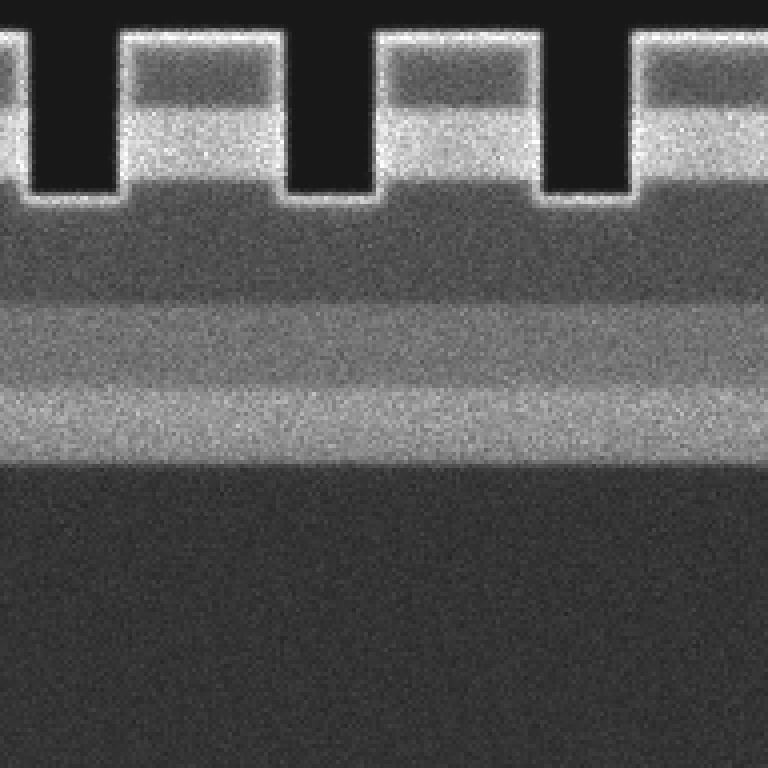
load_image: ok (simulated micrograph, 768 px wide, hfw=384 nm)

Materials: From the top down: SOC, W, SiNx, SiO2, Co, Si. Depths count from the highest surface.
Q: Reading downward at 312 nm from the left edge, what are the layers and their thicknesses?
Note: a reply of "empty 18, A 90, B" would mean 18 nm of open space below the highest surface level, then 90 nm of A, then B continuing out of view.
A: empty 82, SiNx 54, SiO2 42, Co 38, Si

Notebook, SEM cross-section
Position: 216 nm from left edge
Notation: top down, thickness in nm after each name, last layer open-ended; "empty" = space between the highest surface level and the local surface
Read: SOC 38, W 36, SiNx 62, SiO2 42, Co 38, Si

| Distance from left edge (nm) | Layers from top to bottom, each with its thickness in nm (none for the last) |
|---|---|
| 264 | SOC 38, W 36, SiNx 62, SiO2 42, Co 38, Si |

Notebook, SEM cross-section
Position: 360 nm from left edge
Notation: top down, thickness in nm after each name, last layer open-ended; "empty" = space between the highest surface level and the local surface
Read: SOC 38, W 36, SiNx 62, SiO2 42, Co 38, Si